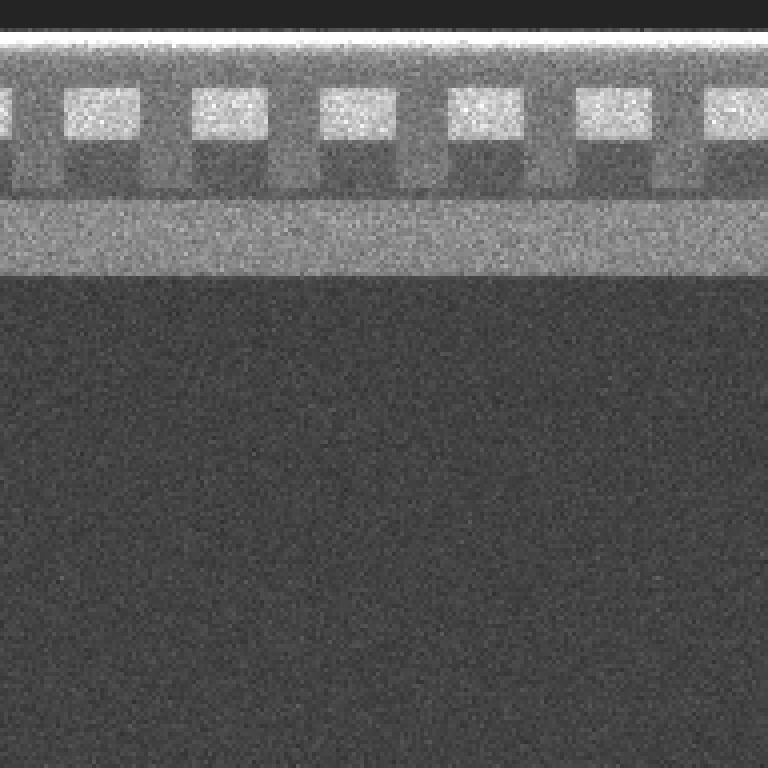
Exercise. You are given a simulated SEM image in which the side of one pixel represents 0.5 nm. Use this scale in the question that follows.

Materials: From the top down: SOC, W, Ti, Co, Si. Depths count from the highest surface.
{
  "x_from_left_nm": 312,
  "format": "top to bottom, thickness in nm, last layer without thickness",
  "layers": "SOC 28, W 26, Ti 30, Co 38, Si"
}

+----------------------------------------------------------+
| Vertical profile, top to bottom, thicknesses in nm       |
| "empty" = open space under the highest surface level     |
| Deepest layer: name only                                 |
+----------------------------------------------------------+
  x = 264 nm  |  SOC 78, Ti 6, Co 38, Si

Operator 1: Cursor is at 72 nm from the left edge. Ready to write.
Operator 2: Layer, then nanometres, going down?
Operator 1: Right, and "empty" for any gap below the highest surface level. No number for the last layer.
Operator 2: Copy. SOC 78, Ti 6, Co 38, Si